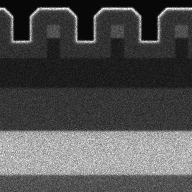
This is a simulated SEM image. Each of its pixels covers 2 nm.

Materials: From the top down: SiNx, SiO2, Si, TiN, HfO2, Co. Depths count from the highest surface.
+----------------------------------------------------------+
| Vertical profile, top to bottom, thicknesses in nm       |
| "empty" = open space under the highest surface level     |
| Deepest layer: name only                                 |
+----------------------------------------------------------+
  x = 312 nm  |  empty 66, SiNx 34, Si 60, TiN 86, HfO2 88, Co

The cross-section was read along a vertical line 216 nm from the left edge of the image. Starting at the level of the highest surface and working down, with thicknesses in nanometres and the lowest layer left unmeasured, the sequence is SiNx 100, Si 60, TiN 86, HfO2 88, Co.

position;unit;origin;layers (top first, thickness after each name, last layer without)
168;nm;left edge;empty 66, SiNx 34, Si 60, TiN 86, HfO2 88, Co